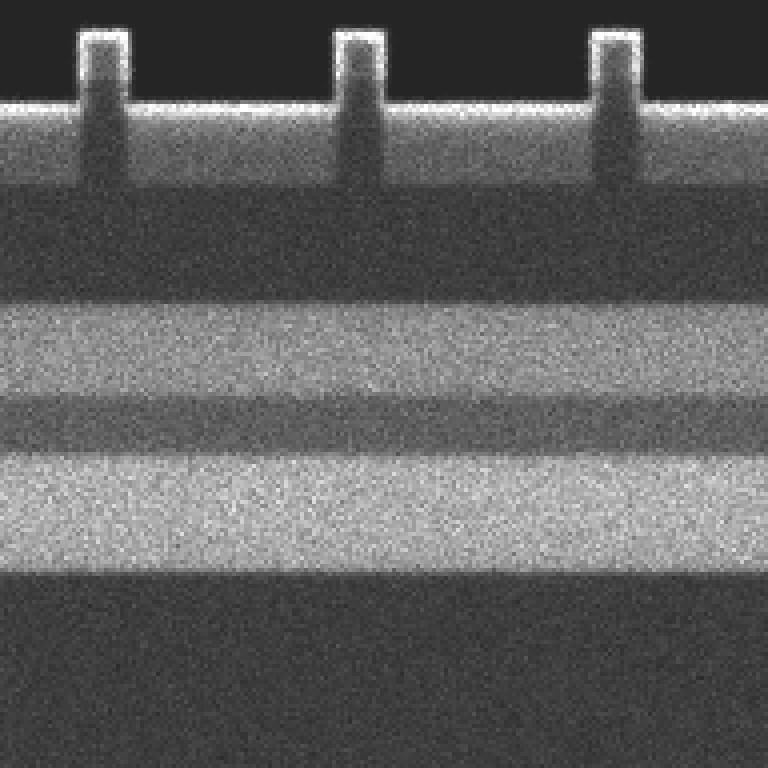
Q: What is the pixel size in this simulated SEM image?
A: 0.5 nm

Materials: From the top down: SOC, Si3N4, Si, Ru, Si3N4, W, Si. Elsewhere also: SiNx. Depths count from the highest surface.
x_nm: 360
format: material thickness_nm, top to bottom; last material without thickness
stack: empty 36, SOC 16, Si3N4 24, Si 60, Ru 46, Si3N4 30, W 58, Si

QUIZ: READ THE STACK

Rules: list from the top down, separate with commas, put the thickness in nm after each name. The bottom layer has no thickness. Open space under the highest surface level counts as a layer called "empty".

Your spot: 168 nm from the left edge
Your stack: SiNx 24, Si 112, Ru 46, Si3N4 30, W 58, Si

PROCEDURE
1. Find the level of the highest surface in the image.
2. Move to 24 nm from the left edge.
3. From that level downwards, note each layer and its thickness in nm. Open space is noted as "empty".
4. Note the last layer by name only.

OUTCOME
empty 36, SOC 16, Si3N4 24, Si 60, Ru 46, Si3N4 30, W 58, Si